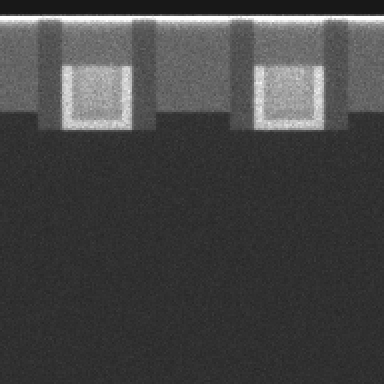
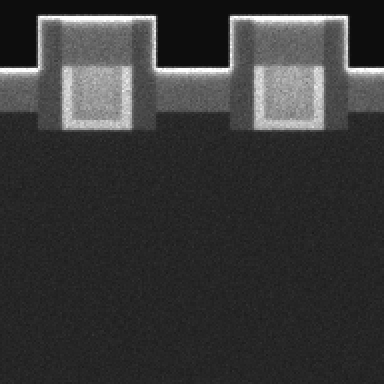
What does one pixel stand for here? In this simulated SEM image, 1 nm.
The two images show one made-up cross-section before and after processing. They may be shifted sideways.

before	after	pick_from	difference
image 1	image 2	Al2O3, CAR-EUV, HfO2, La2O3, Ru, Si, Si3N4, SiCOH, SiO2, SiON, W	SiO2 removed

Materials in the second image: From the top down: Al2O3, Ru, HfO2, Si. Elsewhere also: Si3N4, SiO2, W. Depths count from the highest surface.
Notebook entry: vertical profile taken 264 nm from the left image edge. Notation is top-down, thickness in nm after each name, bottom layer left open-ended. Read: Al2O3 50, Ru 54, HfO2 10, Si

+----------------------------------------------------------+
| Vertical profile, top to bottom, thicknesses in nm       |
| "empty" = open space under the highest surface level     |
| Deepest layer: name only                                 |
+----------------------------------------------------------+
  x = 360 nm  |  empty 52, SiO2 44, Si